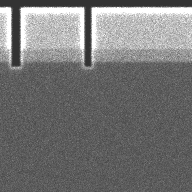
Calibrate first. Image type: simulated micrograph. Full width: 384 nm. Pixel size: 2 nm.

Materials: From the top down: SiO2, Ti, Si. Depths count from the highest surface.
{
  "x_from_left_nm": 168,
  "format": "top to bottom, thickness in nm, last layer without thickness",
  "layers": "empty 118, Si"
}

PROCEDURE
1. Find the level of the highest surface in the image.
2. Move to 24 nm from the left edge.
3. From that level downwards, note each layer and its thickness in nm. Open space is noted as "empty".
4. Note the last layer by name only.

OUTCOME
empty 118, Si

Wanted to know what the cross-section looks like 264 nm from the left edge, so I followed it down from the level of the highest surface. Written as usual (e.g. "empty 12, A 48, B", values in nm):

SiO2 82, Ti 26, Si